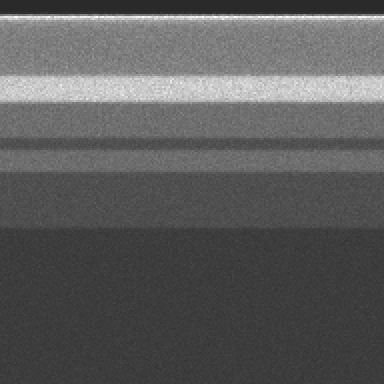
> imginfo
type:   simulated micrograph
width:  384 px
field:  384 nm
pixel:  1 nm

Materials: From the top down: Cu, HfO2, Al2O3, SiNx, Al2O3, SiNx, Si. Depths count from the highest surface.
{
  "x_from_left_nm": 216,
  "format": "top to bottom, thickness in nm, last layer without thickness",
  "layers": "Cu 60, HfO2 26, Al2O3 36, SiNx 12, Al2O3 22, SiNx 56, Si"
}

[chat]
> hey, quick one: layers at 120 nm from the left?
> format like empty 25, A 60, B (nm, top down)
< Cu 60, HfO2 26, Al2O3 36, SiNx 12, Al2O3 22, SiNx 56, Si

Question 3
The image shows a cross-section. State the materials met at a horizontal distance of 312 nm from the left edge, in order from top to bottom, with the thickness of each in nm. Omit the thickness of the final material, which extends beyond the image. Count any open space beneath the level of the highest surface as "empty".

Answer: Cu 60, HfO2 26, Al2O3 36, SiNx 12, Al2O3 22, SiNx 56, Si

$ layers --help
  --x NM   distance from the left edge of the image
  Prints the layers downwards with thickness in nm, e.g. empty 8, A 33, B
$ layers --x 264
Cu 60, HfO2 26, Al2O3 36, SiNx 12, Al2O3 22, SiNx 56, Si